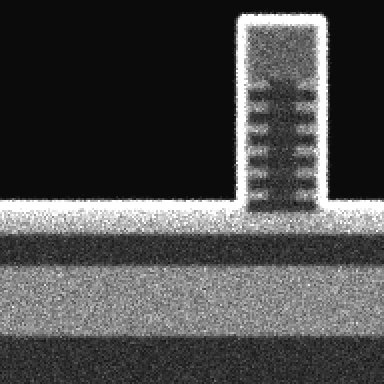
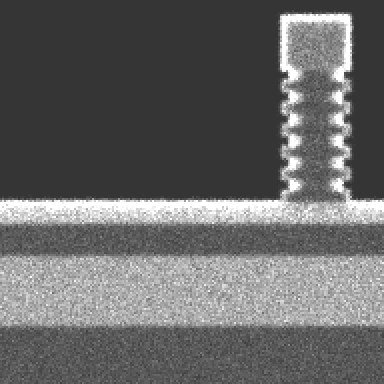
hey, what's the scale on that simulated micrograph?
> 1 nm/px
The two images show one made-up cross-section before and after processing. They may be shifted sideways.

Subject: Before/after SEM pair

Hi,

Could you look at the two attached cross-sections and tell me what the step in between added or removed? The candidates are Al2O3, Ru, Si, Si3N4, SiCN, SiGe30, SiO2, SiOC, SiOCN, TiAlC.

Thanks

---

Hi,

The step removed Al2O3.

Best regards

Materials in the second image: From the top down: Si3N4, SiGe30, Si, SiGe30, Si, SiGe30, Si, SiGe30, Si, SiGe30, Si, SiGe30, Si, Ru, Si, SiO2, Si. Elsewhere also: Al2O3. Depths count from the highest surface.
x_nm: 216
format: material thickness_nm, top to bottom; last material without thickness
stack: empty 186, Ru 22, Si 32, SiO2 70, Si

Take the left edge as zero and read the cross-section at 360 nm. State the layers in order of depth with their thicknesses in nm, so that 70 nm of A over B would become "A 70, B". empty 186, Ru 22, Si 32, SiO2 70, Si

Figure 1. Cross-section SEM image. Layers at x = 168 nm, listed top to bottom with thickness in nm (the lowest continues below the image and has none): empty 186, Ru 22, Si 32, SiO2 70, Si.